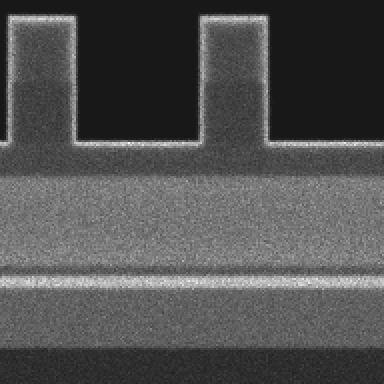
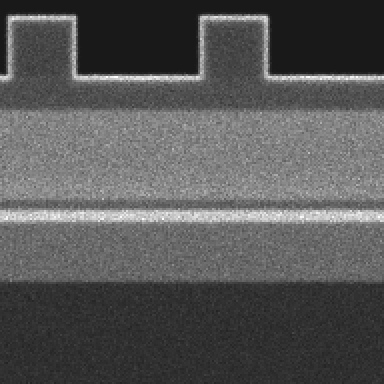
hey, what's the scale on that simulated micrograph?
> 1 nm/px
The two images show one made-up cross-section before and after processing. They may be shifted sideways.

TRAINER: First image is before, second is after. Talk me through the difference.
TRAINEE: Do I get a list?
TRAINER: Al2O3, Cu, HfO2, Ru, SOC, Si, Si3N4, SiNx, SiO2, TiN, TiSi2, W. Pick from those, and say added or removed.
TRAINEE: removed: SOC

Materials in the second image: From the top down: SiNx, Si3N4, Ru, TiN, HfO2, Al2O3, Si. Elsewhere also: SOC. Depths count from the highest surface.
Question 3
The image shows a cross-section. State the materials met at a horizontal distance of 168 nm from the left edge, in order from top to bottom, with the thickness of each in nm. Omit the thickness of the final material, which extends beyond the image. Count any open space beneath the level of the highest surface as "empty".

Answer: empty 60, Si3N4 34, Ru 90, TiN 10, HfO2 12, Al2O3 60, Si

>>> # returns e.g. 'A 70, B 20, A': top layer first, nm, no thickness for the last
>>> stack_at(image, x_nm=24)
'SiNx 60, Si3N4 34, Ru 90, TiN 10, HfO2 12, Al2O3 60, Si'